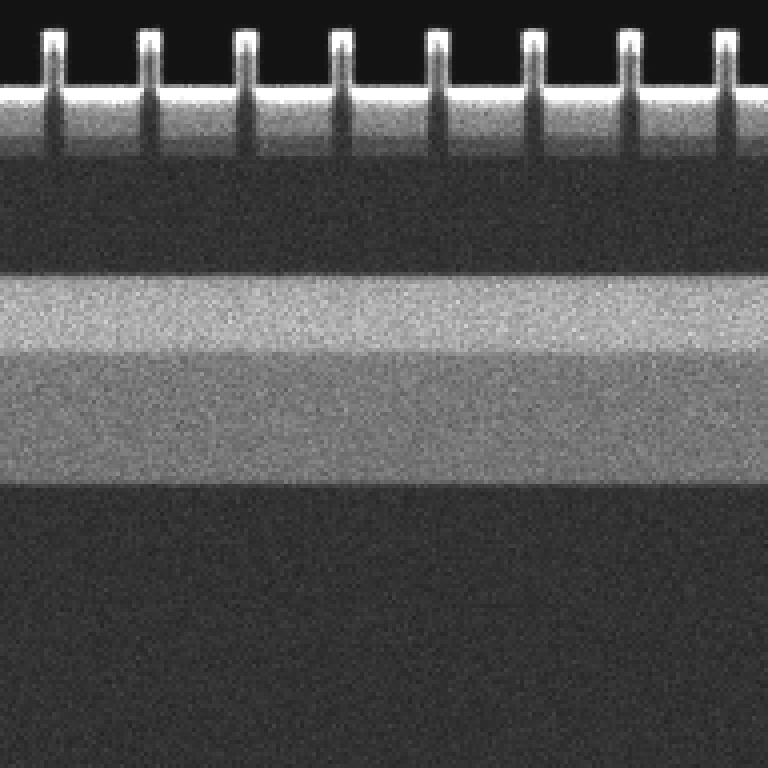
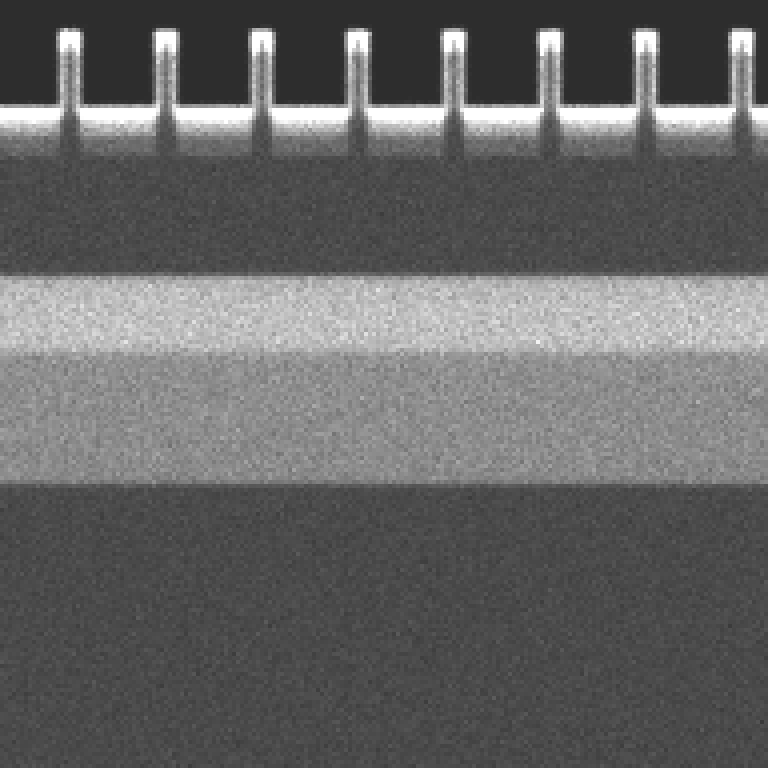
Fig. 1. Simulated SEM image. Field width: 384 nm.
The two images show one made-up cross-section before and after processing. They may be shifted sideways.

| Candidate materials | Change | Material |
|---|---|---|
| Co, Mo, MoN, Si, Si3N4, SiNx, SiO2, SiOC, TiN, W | removed | SiO2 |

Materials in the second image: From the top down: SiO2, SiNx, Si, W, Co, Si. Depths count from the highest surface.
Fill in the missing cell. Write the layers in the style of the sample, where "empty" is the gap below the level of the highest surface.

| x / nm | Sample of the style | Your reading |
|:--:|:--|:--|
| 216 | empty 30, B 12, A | empty 38, SiO2 14, SiNx 10, Si 60, W 38, Co 66, Si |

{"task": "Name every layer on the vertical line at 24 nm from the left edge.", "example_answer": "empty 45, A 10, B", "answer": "empty 38, SiO2 14, SiNx 10, Si 60, W 38, Co 66, Si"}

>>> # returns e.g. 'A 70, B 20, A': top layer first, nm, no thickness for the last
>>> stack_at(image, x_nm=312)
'empty 38, SiO2 14, SiNx 10, Si 60, W 38, Co 66, Si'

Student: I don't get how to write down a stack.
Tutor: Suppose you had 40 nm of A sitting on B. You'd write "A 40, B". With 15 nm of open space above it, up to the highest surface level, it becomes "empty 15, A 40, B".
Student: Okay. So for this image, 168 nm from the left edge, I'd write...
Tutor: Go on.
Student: empty 38, SiO2 14, SiNx 10, Si 60, W 38, Co 66, Si